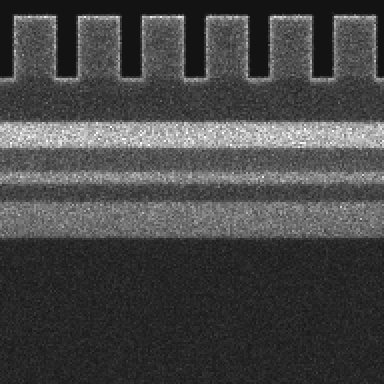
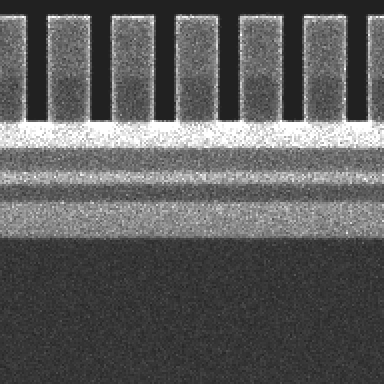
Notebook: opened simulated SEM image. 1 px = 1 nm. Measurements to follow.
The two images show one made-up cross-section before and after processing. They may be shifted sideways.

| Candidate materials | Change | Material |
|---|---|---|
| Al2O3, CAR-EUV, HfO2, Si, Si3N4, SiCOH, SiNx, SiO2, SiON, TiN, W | removed | SiNx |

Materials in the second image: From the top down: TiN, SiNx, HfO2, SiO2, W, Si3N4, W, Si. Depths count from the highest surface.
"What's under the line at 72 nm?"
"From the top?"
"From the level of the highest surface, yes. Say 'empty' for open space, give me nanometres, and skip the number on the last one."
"TiN 62, SiNx 44, HfO2 26, SiO2 24, W 12, Si3N4 18, W 36, Si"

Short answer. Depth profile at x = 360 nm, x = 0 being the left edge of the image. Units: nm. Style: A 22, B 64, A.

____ empty 106, HfO2 26, SiO2 24, W 12, Si3N4 18, W 36, Si